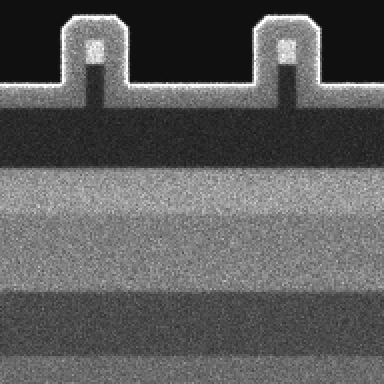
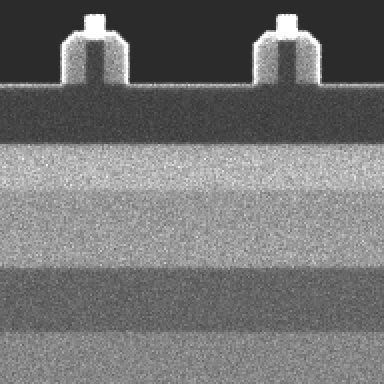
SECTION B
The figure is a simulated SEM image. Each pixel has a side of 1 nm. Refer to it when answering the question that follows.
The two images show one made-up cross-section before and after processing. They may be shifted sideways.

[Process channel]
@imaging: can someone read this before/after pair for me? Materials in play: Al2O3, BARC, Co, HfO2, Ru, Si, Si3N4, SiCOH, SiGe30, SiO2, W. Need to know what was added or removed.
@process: Co removed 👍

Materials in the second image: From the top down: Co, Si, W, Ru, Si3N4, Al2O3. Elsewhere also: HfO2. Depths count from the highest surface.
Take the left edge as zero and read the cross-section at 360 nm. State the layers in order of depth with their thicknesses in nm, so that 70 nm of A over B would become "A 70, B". empty 68, Si 60, W 46, Ru 78, Si3N4 64, Al2O3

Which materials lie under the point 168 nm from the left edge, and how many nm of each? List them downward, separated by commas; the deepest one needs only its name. empty 68, Si 60, W 46, Ru 78, Si3N4 64, Al2O3